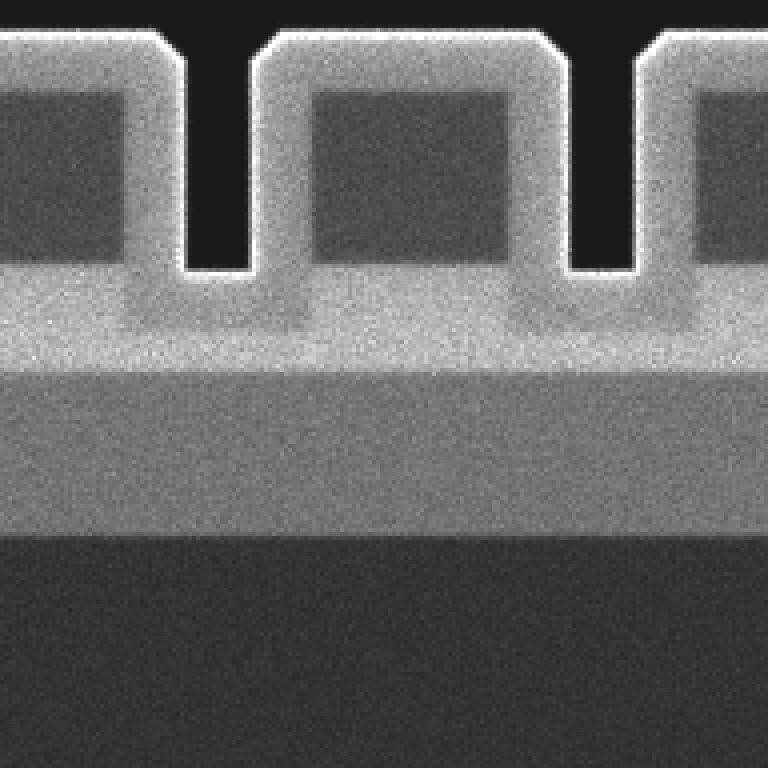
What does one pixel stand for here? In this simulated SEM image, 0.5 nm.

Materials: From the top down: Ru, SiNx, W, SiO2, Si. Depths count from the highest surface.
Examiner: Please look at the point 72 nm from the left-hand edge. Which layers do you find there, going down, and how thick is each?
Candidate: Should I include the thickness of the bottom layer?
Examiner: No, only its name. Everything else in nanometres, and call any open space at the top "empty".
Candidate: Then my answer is Ru 150, W 20, SiO2 82, Si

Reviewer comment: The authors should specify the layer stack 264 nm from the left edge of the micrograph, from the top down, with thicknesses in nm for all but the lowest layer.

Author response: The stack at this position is Ru 150, W 20, SiO2 82, Si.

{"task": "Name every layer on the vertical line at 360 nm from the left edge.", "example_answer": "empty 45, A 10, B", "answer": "Ru 30, SiNx 86, W 54, SiO2 82, Si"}